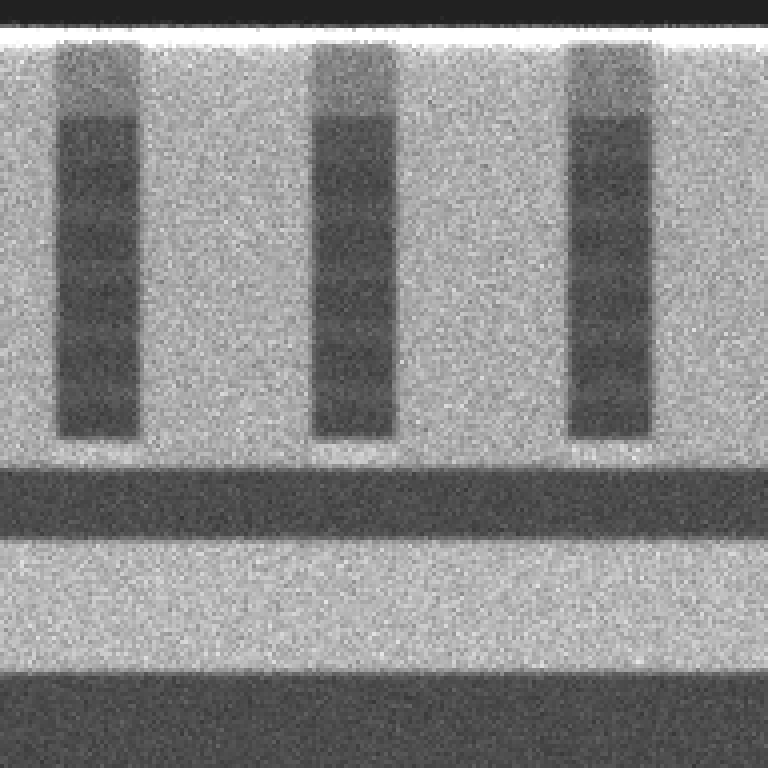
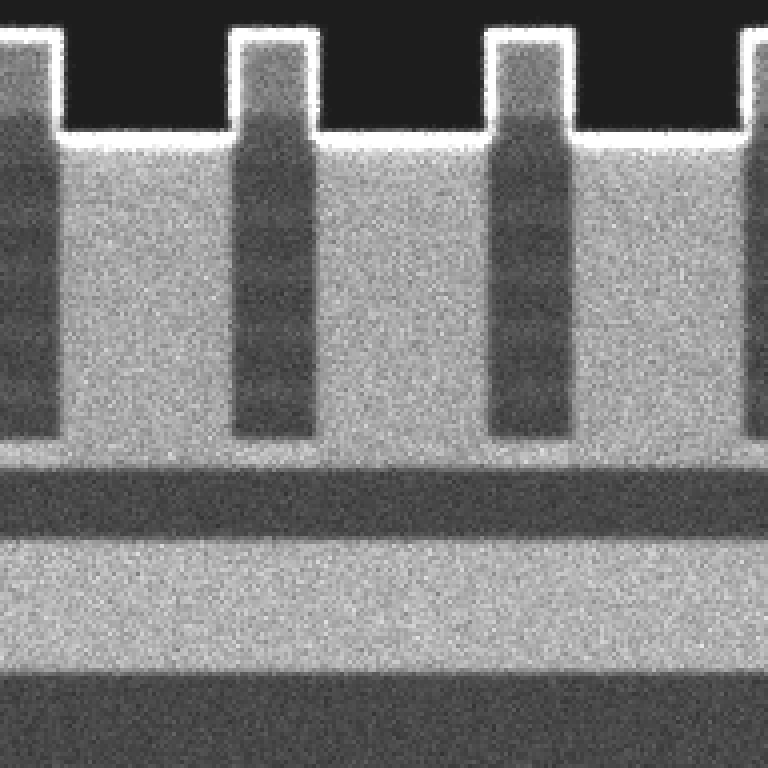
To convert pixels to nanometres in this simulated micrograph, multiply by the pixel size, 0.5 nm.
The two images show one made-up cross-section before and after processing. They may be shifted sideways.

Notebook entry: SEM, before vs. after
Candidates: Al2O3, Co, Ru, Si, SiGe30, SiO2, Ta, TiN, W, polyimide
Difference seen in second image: Co removed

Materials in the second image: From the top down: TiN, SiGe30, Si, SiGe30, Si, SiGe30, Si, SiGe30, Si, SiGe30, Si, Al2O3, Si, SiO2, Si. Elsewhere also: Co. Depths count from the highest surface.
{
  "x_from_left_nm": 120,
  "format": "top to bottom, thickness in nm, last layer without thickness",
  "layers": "TiN 42, SiGe30 24, Si 18, SiGe30 12, Si 18, SiGe30 12, Si 18, SiGe30 12, Si 18, SiGe30 12, Si 18, Al2O3 14, Si 36, SiO2 66, Si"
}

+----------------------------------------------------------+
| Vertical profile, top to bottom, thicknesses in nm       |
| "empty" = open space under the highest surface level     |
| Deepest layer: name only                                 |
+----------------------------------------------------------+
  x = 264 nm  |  TiN 42, SiGe30 24, Si 18, SiGe30 12, Si 18, SiGe30 12, Si 18, SiGe30 12, Si 18, SiGe30 12, Si 18, Al2O3 14, Si 36, SiO2 66, Si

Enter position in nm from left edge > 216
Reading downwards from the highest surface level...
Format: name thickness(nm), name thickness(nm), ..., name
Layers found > empty 52, Co 166, Si 36, SiO2 66, Si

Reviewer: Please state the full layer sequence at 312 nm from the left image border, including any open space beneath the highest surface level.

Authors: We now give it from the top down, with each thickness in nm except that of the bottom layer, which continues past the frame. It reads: empty 52, Co 166, Si 36, SiO2 66, Si